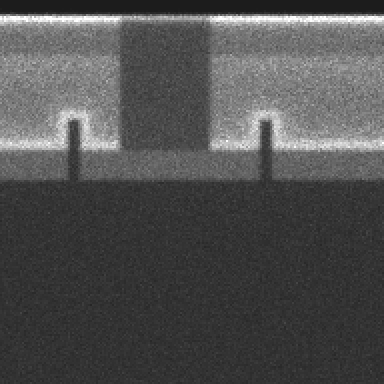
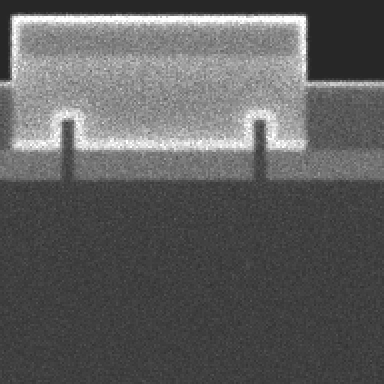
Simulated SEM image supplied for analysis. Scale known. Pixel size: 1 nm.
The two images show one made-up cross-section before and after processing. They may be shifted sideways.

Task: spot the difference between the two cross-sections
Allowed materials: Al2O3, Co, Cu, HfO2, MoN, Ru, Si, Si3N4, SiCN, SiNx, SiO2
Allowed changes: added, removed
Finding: removed SiNx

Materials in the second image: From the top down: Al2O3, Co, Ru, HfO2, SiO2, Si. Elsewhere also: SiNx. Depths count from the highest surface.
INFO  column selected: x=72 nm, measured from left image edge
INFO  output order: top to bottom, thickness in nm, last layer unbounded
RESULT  Al2O3 40, Co 42, Ru 12, HfO2 10, Si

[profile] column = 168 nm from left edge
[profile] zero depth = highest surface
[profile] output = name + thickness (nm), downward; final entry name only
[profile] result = Al2O3 40, Co 72, Ru 12, HfO2 10, SiO2 30, Si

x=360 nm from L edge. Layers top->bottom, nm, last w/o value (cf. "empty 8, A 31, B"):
empty 66, SiNx 68, SiO2 30, Si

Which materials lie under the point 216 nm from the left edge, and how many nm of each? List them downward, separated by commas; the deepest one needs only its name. Al2O3 40, Co 72, Ru 12, HfO2 10, SiO2 30, Si